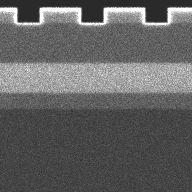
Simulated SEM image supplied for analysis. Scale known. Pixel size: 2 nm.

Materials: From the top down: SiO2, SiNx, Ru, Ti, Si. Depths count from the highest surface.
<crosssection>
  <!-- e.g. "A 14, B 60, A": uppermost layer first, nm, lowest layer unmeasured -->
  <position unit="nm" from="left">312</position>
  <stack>empty 30, SiNx 80, Ru 60, Ti 32, Si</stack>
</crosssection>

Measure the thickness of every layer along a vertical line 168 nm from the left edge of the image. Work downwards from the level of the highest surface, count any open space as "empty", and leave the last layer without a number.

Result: empty 30, SiNx 80, Ru 60, Ti 32, Si